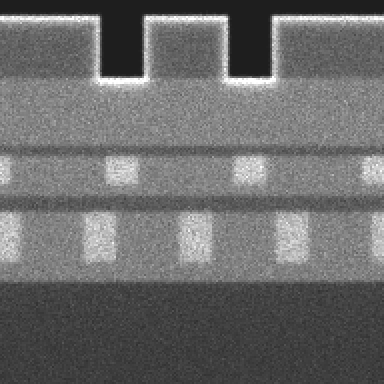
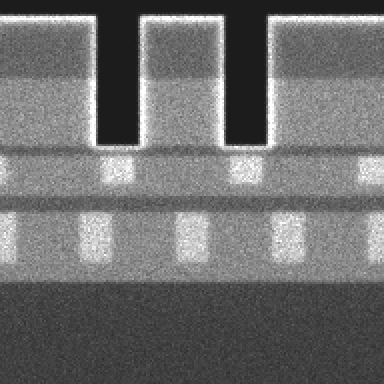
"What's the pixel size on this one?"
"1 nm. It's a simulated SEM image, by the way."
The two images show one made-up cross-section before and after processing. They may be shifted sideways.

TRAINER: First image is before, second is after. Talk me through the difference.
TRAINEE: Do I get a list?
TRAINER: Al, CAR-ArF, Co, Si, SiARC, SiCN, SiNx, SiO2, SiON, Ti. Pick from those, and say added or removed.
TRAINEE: removed: SiO2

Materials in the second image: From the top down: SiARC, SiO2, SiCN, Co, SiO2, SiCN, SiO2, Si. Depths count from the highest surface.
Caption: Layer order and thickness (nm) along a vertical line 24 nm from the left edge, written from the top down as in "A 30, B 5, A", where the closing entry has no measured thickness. SiARC 62, SiO2 68, SiCN 10, SiO2 40, SiCN 16, SiO2 70, Si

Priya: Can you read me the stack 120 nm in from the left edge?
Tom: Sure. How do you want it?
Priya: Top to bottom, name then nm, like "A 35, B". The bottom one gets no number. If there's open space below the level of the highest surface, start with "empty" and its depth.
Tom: empty 130, SiCN 10, Co 28, SiO2 12, SiCN 16, SiO2 70, Si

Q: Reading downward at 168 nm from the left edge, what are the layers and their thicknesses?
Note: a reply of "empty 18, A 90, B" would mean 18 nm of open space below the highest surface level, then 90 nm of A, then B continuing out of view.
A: SiARC 62, SiO2 68, SiCN 10, SiO2 40, SiCN 16, SiO2 70, Si